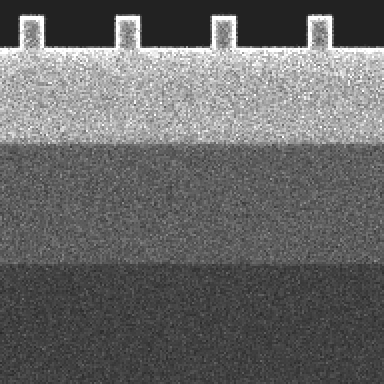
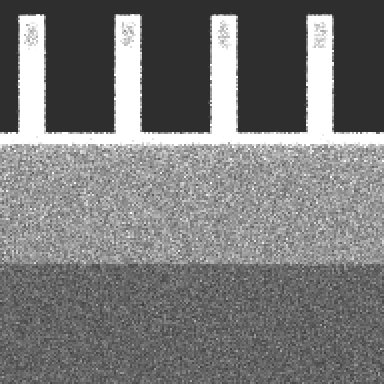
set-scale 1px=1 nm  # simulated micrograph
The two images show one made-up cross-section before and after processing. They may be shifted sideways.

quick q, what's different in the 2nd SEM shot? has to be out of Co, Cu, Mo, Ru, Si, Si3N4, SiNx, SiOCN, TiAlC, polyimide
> Ru removed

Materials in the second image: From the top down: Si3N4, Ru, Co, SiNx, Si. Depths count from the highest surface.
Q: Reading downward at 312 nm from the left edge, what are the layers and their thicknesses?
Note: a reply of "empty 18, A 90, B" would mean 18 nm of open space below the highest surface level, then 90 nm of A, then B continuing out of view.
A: Si3N4 32, Ru 86, Co 10, SiNx 120, Si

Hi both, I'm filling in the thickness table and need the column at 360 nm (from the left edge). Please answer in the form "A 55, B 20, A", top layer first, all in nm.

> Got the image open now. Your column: empty 118, Co 10, SiNx 120, Si